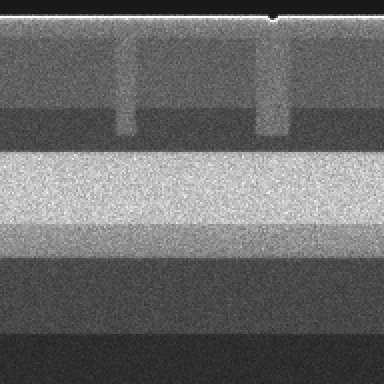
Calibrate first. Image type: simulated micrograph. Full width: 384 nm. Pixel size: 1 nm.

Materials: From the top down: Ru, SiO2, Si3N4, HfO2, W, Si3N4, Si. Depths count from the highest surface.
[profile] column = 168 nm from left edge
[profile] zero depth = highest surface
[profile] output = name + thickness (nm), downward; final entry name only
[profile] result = Ru 22, SiO2 70, Si3N4 44, HfO2 72, W 34, Si3N4 76, Si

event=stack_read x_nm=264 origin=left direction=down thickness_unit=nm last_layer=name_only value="Ru 120, Si3N4 16, HfO2 72, W 34, Si3N4 76, Si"